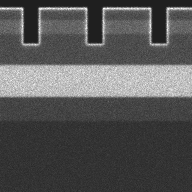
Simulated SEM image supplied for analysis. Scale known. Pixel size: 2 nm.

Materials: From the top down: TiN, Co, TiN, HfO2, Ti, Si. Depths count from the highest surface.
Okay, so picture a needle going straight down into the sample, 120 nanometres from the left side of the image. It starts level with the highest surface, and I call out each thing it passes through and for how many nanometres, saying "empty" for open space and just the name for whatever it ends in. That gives TiN 24, Co 28, TiN 62, HfO2 64, Ti 48, Si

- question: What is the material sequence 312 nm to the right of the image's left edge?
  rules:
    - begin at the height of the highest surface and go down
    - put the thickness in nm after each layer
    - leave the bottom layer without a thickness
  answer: empty 72, TiN 42, HfO2 64, Ti 48, Si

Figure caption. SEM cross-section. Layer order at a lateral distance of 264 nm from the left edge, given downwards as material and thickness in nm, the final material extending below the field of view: TiN 24, Co 28, TiN 62, HfO2 64, Ti 48, Si